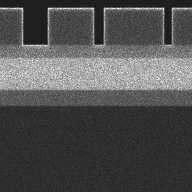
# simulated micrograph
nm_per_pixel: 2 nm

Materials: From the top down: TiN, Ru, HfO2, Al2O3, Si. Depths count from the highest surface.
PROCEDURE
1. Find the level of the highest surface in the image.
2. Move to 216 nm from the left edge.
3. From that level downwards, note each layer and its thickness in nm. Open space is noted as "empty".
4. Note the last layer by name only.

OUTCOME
TiN 74, Ru 26, HfO2 64, Al2O3 32, Si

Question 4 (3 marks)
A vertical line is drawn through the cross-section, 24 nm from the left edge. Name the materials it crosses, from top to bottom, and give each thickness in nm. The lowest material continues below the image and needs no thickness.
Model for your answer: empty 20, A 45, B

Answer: TiN 74, Ru 26, HfO2 64, Al2O3 32, Si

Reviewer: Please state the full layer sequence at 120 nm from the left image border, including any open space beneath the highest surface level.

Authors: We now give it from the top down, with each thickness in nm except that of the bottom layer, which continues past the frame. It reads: TiN 74, Ru 26, HfO2 64, Al2O3 32, Si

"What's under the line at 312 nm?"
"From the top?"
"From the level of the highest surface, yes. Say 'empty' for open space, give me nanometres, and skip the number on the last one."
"TiN 74, Ru 26, HfO2 64, Al2O3 32, Si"